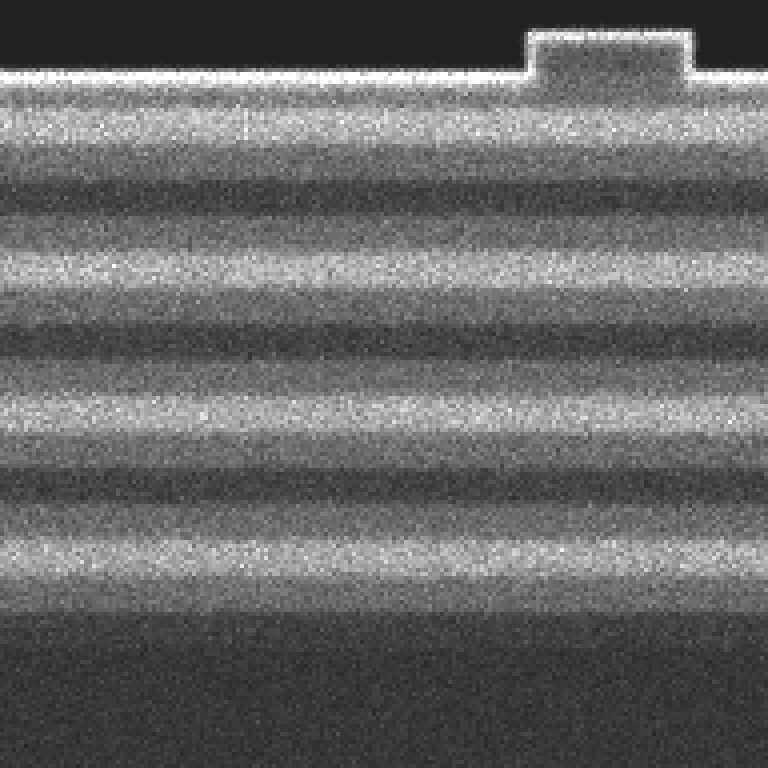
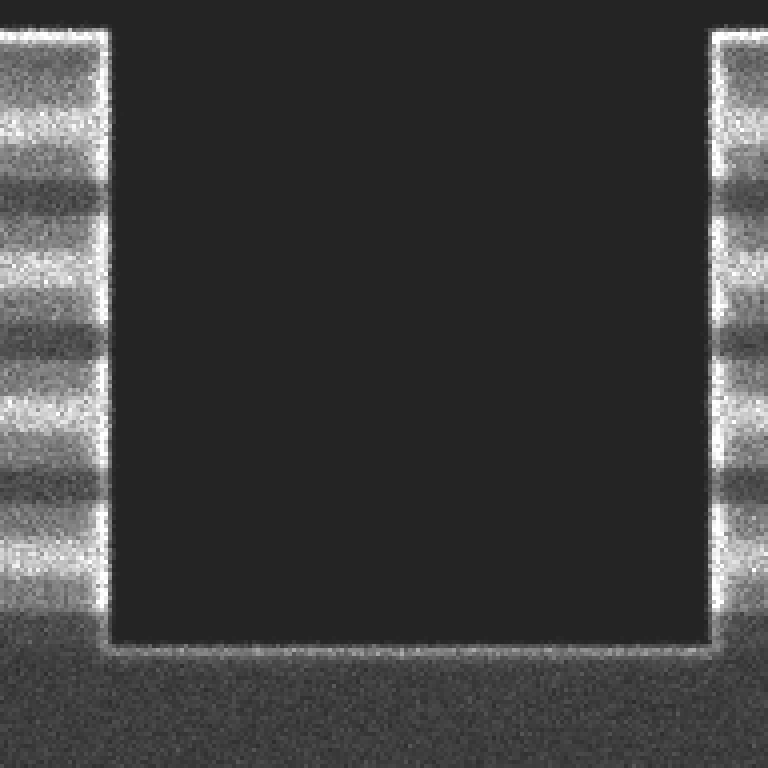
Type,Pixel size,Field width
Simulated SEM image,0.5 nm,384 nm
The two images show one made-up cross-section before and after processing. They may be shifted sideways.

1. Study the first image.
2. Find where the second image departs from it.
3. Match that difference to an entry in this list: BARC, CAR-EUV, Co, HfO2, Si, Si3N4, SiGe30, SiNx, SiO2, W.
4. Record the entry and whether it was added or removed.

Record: SiGe30 and SiO2 and W / removed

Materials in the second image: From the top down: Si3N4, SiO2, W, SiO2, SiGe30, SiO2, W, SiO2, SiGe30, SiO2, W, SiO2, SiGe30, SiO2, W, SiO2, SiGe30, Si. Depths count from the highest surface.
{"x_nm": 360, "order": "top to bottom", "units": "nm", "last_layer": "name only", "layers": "Si3N4 20, SiO2 18, W 18, SiO2 18, SiGe30 18, SiO2 18, W 18, SiO2 18, SiGe30 18, SiO2 18, W 18, SiO2 18, SiGe30 18, SiO2 18, W 18, SiO2 18, SiGe30 18, Si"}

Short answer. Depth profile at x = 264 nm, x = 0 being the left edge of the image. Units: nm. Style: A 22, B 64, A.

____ empty 308, Si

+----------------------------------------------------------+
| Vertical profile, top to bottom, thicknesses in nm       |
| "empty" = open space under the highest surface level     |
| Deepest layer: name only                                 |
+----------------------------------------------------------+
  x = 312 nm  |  empty 308, Si